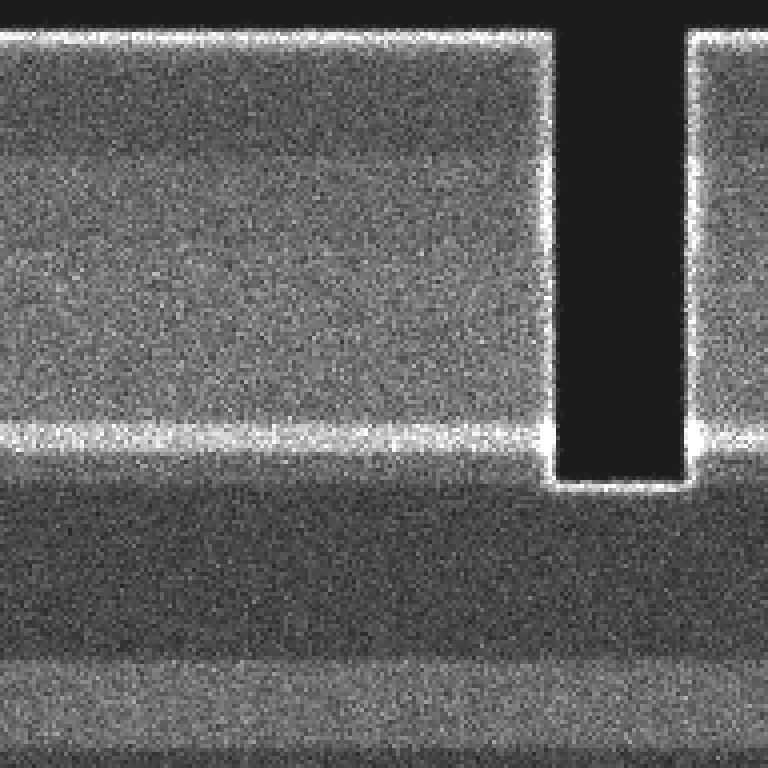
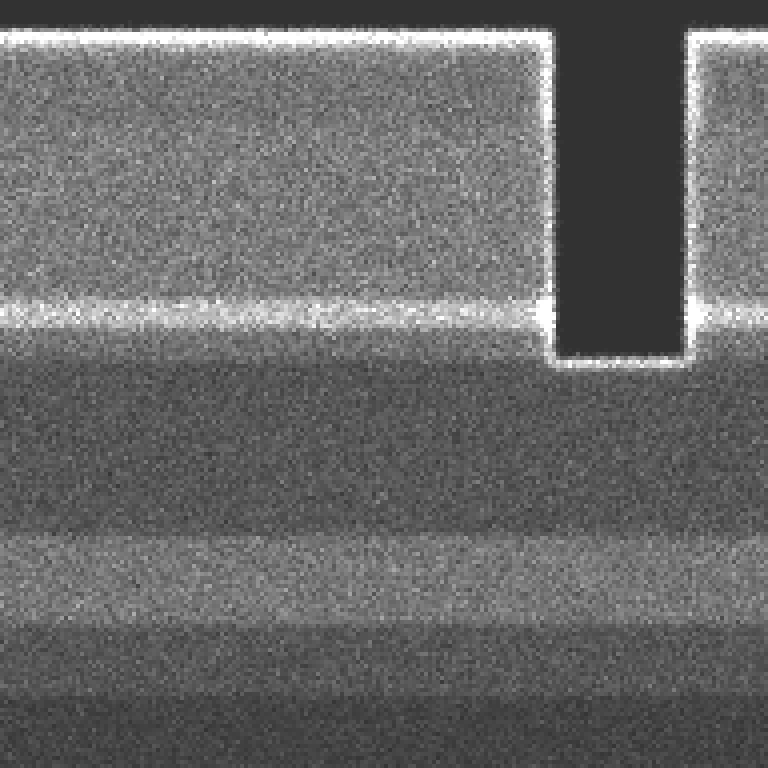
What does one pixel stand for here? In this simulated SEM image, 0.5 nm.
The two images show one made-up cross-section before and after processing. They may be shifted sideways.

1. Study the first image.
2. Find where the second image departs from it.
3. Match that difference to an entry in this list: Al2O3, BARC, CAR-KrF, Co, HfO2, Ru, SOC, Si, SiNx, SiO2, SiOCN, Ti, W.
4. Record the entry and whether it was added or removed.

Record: SOC / removed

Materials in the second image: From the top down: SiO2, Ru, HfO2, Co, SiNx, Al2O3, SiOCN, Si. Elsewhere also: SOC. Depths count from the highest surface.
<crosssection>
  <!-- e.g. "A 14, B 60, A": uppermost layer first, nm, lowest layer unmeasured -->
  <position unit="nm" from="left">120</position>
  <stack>SiO2 46, Ru 88, HfO2 14, Co 16, SiNx 88, Al2O3 44, SiOCN 36, Si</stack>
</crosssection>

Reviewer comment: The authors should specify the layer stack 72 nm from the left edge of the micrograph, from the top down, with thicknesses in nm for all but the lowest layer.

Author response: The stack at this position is SiO2 46, Ru 88, HfO2 14, Co 16, SiNx 88, Al2O3 44, SiOCN 36, Si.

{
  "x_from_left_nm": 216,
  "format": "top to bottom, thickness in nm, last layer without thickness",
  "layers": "SiO2 46, Ru 88, HfO2 14, Co 16, SiNx 88, Al2O3 44, SiOCN 36, Si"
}